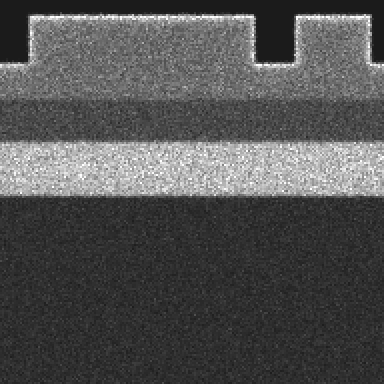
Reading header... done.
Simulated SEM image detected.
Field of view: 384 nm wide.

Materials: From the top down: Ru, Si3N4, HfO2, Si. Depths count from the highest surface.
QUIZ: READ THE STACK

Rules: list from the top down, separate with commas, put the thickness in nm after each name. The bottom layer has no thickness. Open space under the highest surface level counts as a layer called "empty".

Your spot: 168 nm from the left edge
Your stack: Ru 84, Si3N4 42, HfO2 54, Si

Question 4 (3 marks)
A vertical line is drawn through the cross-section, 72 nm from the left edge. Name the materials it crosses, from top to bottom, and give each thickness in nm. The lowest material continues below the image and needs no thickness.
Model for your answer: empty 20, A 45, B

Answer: Ru 84, Si3N4 42, HfO2 54, Si